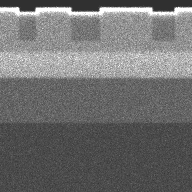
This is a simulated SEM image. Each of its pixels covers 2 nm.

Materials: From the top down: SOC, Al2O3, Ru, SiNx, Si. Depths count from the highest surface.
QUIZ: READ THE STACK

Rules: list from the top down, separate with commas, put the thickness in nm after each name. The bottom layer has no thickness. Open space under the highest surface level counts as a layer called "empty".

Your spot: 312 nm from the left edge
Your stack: empty 8, SOC 58, Al2O3 22, Ru 52, SiNx 90, Si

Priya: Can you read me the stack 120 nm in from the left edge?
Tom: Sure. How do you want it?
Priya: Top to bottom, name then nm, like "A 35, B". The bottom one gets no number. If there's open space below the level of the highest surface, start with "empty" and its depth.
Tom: Al2O3 88, Ru 52, SiNx 90, Si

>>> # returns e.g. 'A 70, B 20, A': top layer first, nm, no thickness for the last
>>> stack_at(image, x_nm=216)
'Al2O3 88, Ru 52, SiNx 90, Si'